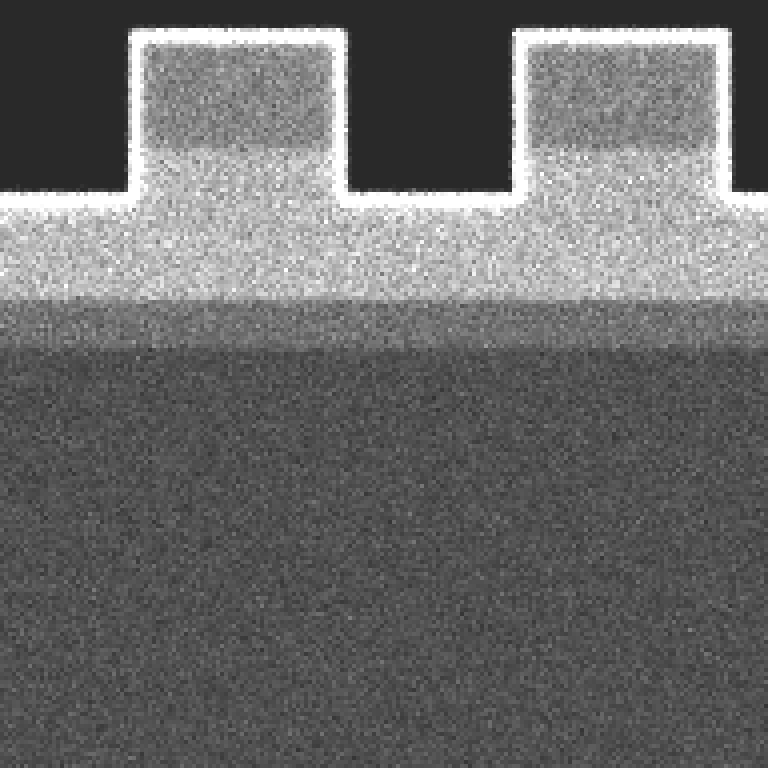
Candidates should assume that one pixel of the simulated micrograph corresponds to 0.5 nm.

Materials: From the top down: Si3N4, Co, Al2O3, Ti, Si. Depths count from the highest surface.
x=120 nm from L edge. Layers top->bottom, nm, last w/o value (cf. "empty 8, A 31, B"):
Si3N4 58, Co 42, Al2O3 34, Ti 24, Si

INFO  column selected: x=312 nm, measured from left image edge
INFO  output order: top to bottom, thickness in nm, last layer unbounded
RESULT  Si3N4 58, Co 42, Al2O3 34, Ti 24, Si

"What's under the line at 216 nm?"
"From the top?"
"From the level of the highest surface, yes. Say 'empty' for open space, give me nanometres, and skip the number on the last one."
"empty 82, Co 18, Al2O3 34, Ti 24, Si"